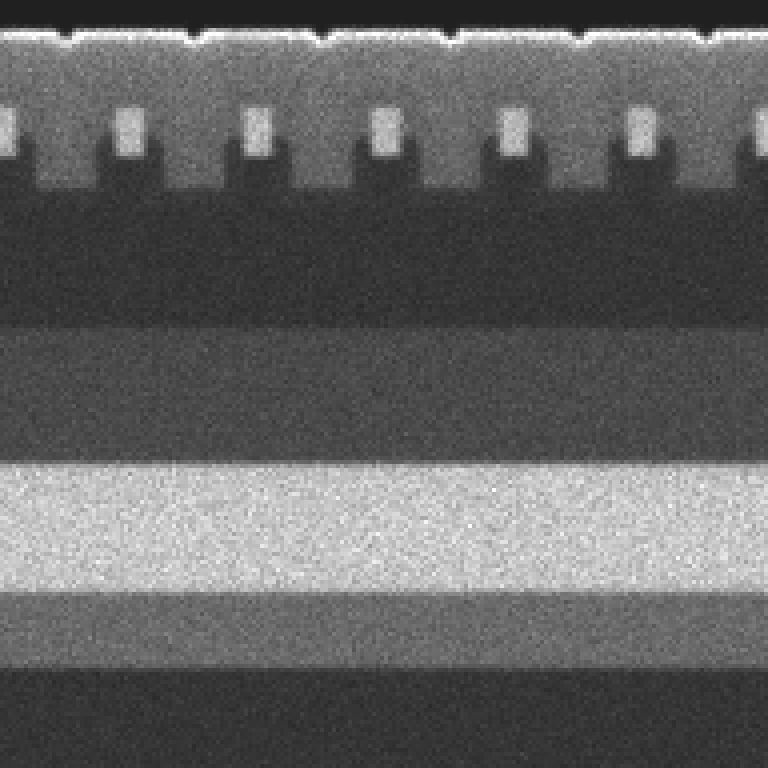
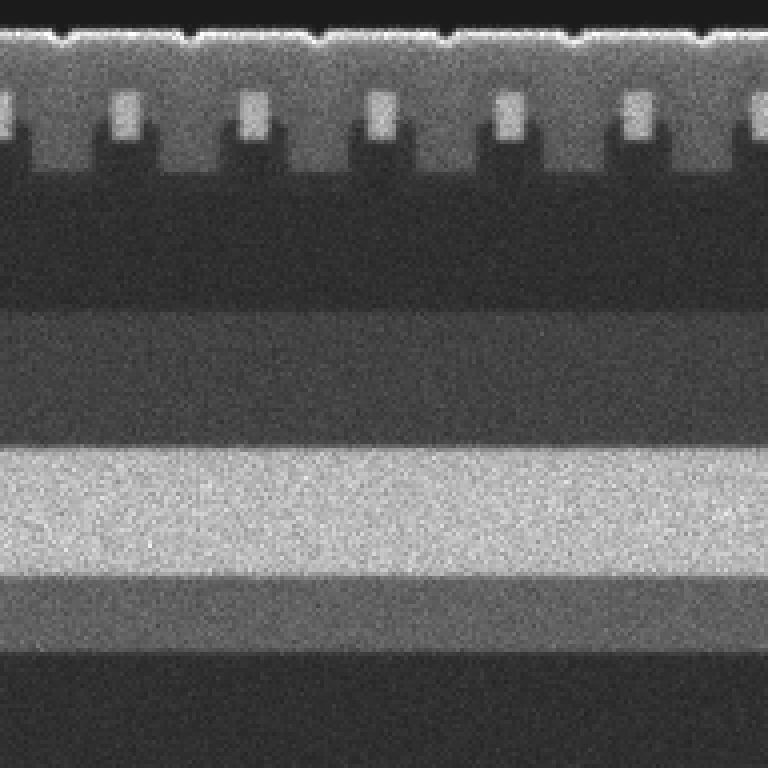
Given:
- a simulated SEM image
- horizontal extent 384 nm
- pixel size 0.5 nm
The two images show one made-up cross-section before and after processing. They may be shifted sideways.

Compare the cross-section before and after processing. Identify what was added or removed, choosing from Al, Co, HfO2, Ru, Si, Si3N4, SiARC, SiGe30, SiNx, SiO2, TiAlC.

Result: Ru removed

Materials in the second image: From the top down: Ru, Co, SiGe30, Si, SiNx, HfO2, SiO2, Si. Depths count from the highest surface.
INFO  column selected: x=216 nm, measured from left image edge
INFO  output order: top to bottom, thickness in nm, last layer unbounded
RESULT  Ru 40, Co 30, SiGe30 10, Si 60, SiNx 68, HfO2 64, SiO2 38, Si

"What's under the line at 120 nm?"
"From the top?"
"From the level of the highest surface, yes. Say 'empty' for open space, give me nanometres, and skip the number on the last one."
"Ru 18, Co 12, HfO2 24, Si 86, SiNx 68, HfO2 64, SiO2 38, Si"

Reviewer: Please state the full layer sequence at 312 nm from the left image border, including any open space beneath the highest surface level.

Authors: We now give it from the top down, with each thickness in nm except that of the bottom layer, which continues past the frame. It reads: Ru 18, Co 12, HfO2 24, Si 86, SiNx 68, HfO2 64, SiO2 38, Si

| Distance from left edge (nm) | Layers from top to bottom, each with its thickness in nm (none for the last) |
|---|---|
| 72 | Ru 18, Co 26, SiGe30 36, Si 60, SiNx 68, HfO2 64, SiO2 38, Si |